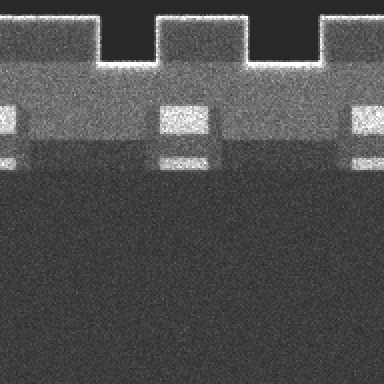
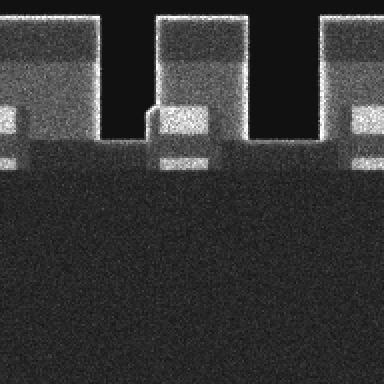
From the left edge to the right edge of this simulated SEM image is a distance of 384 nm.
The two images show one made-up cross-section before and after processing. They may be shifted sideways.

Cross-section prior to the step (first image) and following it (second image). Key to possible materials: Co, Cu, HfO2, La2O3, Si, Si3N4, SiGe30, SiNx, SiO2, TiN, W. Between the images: SiO2 was removed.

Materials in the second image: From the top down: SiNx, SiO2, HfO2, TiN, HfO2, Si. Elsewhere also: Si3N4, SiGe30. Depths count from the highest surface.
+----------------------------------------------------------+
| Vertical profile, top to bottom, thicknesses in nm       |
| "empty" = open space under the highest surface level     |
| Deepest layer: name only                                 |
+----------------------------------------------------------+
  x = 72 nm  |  SiNx 46, SiO2 78, SiGe30 30, Si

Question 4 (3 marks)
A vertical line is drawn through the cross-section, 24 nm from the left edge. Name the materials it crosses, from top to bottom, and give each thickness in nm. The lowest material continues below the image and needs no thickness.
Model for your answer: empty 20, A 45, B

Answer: SiNx 46, SiO2 46, Si3N4 62, Si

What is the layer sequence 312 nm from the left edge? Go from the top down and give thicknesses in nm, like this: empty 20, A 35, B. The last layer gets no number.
empty 124, SiGe30 30, Si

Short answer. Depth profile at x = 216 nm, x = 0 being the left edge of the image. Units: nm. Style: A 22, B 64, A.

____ SiNx 46, SiO2 46, Si3N4 62, Si